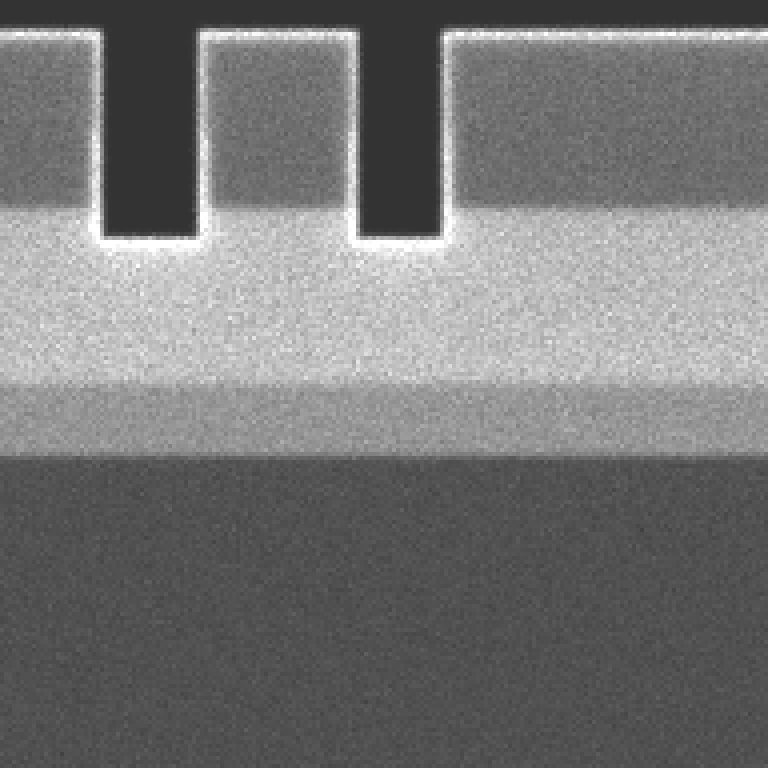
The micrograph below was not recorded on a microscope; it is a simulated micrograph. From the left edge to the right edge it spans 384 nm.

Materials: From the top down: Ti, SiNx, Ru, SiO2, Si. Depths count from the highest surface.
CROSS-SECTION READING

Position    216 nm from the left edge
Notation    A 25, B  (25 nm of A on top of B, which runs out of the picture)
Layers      empty 104, Ru 72, SiO2 36, Si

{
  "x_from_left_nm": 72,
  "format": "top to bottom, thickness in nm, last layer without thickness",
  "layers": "empty 104, Ru 72, SiO2 36, Si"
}